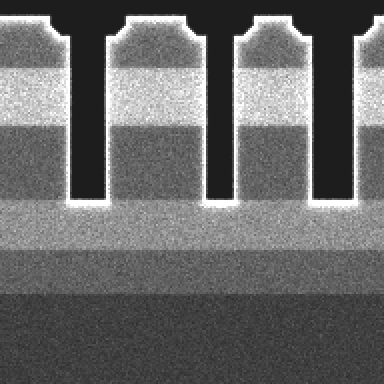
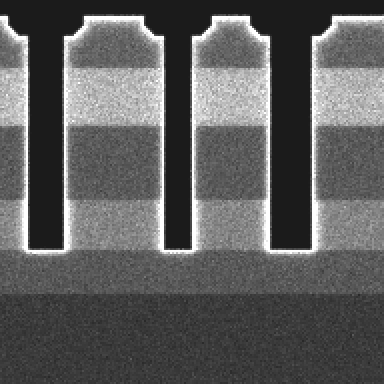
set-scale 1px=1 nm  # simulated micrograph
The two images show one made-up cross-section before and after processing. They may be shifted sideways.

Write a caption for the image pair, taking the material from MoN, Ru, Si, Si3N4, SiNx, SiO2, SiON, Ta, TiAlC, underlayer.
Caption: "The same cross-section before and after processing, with SiO2 removed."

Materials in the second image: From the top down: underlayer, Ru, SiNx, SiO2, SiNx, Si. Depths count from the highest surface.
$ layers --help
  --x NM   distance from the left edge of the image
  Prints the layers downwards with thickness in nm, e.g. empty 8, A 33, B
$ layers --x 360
underlayer 52, Ru 58, SiNx 74, SiO2 50, SiNx 44, Si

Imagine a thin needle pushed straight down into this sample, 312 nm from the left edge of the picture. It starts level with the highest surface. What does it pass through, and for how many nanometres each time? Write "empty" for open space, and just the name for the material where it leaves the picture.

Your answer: empty 20, underlayer 32, Ru 58, SiNx 74, SiO2 50, SiNx 44, Si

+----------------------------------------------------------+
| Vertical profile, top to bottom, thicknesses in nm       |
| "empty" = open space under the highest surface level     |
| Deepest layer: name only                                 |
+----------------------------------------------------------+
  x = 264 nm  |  empty 20, underlayer 32, Ru 58, SiNx 74, SiO2 50, SiNx 44, Si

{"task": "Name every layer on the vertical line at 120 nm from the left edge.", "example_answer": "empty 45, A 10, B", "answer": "underlayer 52, Ru 58, SiNx 74, SiO2 50, SiNx 44, Si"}